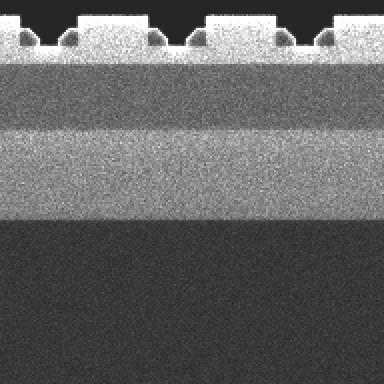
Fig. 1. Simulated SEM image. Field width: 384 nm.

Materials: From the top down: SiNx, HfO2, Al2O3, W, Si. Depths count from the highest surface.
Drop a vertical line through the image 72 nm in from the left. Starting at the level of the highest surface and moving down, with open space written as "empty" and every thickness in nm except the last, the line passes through empty 12, SiNx 18, HfO2 18, Al2O3 66, W 90, Si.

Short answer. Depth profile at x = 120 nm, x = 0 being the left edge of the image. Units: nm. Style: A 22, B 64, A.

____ HfO2 48, Al2O3 66, W 90, Si